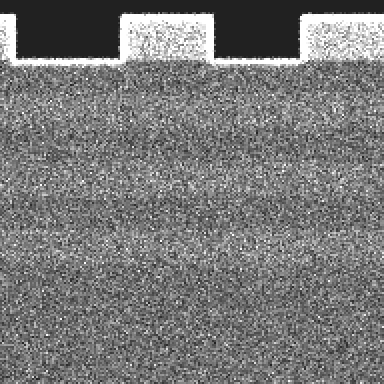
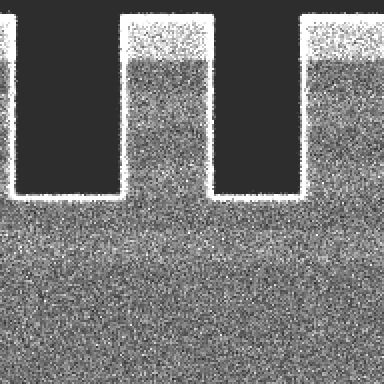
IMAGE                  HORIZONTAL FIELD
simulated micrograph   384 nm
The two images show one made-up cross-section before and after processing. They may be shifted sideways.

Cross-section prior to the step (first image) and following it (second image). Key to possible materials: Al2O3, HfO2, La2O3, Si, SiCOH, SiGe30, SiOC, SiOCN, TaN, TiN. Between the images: Si and SiGe30 was removed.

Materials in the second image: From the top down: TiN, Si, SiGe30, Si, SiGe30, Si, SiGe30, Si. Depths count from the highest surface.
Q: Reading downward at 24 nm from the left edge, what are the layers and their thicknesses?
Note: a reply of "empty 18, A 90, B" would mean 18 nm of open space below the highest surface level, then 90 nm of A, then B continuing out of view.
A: empty 180, Si 34, SiGe30 34, Si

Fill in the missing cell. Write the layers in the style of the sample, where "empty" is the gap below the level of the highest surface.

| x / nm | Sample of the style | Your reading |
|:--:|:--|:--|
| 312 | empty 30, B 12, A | TiN 44, Si 34, SiGe30 34, Si 34, SiGe30 34, Si 34, SiGe30 34, Si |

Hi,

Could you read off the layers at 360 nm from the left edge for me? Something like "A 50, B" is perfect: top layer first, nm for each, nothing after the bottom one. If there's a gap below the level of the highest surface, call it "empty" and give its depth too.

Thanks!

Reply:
TiN 44, Si 34, SiGe30 34, Si 34, SiGe30 34, Si 34, SiGe30 34, Si